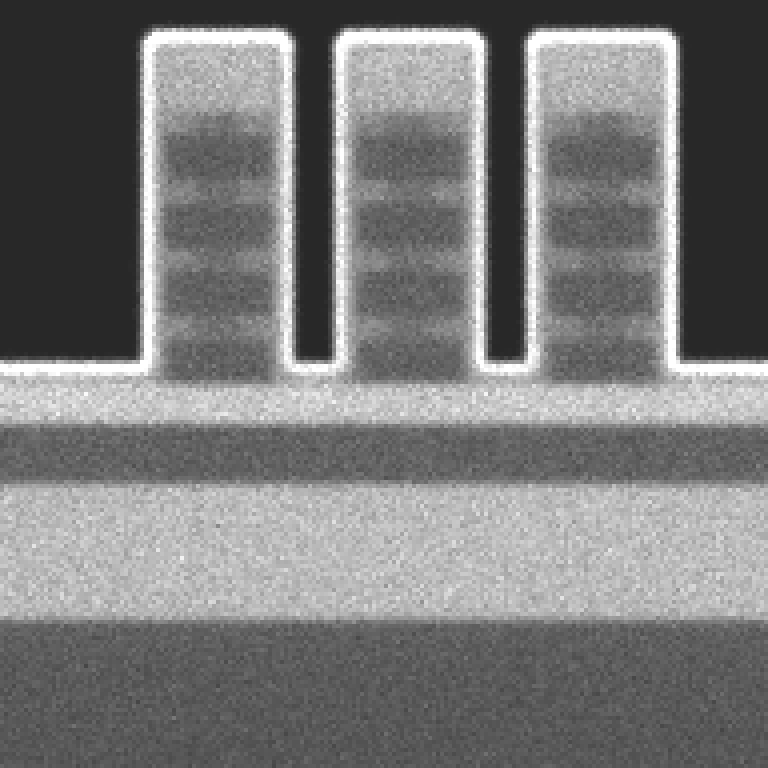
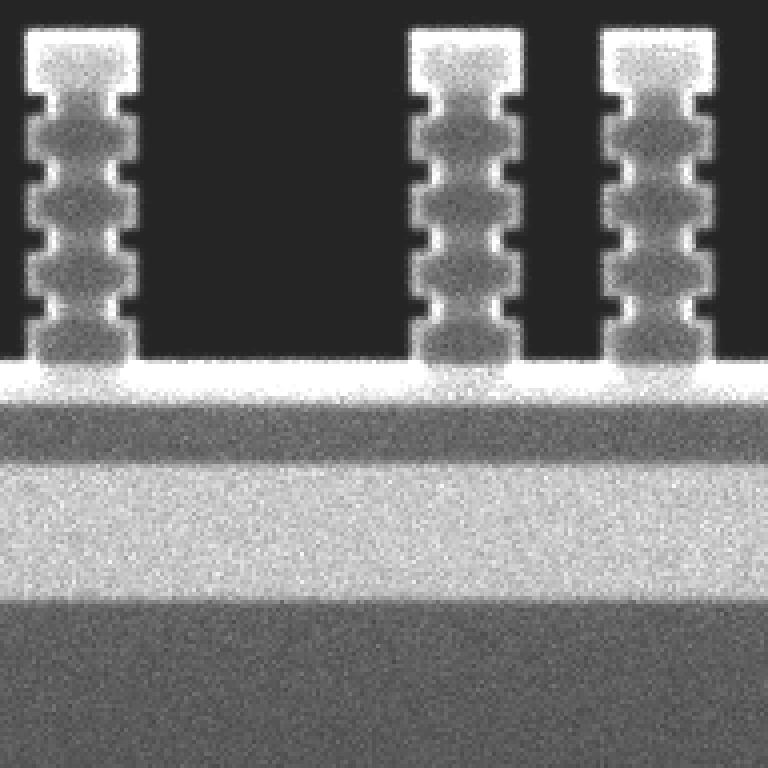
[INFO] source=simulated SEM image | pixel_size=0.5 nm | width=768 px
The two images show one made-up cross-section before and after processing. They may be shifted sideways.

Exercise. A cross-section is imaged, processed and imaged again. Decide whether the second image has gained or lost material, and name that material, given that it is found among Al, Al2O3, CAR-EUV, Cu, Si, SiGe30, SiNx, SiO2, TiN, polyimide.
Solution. removed: SiNx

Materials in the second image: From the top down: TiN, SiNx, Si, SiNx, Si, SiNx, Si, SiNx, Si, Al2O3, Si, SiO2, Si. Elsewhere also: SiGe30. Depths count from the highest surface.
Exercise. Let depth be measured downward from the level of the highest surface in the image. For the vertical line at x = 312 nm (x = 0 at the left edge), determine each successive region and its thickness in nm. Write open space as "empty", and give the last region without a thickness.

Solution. TiN 30, SiNx 12, Si 22, SiNx 12, Si 22, SiNx 12, Si 22, SiNx 12, Si 22, Al2O3 20, Si 30, SiO2 68, Si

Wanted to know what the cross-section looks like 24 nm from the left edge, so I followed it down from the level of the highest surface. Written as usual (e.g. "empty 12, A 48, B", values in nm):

TiN 30, SiNx 12, Si 22, SiNx 12, Si 22, SiNx 12, Si 22, SiNx 12, Si 22, Al2O3 20, Si 30, SiO2 68, Si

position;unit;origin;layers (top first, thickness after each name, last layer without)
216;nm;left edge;TiN 30, SiNx 12, Si 22, SiNx 12, Si 22, SiNx 12, Si 22, SiNx 12, Si 22, Al2O3 20, Si 30, SiO2 68, Si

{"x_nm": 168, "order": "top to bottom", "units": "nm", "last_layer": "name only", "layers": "empty 166, Al2O3 20, Si 30, SiO2 68, Si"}